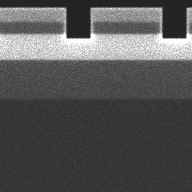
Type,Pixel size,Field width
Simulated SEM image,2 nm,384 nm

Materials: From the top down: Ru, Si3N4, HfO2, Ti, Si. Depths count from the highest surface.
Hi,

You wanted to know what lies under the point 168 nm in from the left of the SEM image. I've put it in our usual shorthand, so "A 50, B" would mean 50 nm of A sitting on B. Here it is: empty 62, HfO2 42, Ti 78, Si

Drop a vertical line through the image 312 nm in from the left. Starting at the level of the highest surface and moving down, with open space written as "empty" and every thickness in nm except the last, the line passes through Ru 28, Si3N4 24, HfO2 52, Ti 78, Si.